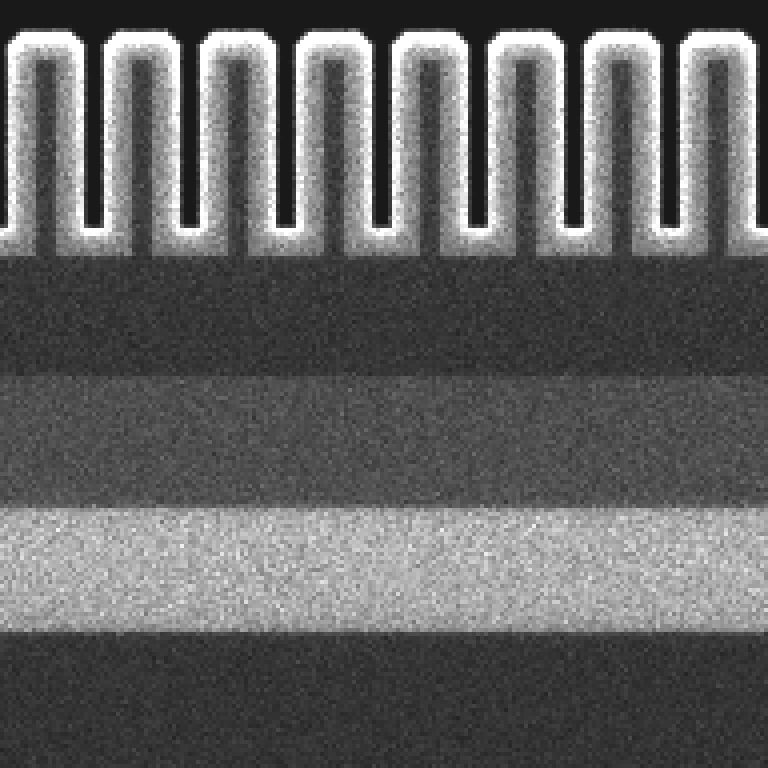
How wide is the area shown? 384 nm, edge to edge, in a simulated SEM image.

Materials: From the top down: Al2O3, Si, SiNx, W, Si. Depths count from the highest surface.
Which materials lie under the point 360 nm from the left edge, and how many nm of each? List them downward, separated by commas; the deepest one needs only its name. Al2O3 14, Si 158, SiNx 66, W 62, Si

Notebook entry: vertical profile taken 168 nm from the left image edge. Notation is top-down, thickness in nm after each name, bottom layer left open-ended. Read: Al2O3 14, Si 158, SiNx 66, W 62, Si